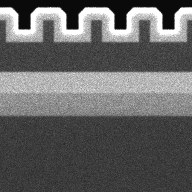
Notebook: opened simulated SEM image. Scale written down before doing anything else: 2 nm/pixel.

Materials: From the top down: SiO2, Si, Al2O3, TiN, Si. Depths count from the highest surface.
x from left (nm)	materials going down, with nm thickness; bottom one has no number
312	empty 2, SiO2 66, Si 60, Al2O3 42, TiN 46, Si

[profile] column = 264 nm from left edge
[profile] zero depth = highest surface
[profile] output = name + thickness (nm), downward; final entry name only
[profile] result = empty 2, SiO2 66, Si 60, Al2O3 42, TiN 46, Si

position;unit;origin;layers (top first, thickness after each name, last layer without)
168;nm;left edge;empty 2, SiO2 66, Si 60, Al2O3 42, TiN 46, Si